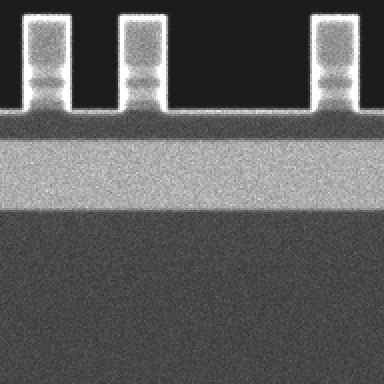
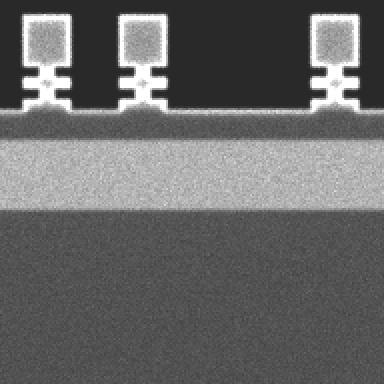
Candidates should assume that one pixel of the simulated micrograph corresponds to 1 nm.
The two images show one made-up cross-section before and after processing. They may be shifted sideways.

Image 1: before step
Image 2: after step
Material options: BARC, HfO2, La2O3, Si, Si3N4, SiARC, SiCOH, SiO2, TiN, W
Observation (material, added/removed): SiO2, removed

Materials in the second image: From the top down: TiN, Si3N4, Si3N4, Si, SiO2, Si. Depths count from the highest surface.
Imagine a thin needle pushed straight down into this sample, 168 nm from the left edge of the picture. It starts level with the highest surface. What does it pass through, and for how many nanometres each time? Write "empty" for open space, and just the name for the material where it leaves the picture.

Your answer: empty 94, Si 30, SiO2 70, Si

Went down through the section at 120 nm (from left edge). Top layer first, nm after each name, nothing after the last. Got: TiN 50, empty 12, Si3N4 10, empty 12, Si3N4 10, Si 30, SiO2 70, Si